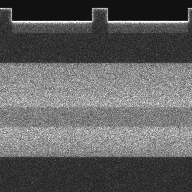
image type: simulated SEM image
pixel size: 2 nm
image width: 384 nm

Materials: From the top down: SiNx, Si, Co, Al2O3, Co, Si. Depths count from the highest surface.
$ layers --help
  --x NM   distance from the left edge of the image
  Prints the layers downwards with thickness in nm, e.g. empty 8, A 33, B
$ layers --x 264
empty 26, SiNx 24, Si 60, Co 88, Al2O3 40, Co 60, Si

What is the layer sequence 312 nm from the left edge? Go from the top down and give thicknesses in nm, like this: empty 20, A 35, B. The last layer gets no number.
empty 26, SiNx 24, Si 60, Co 88, Al2O3 40, Co 60, Si